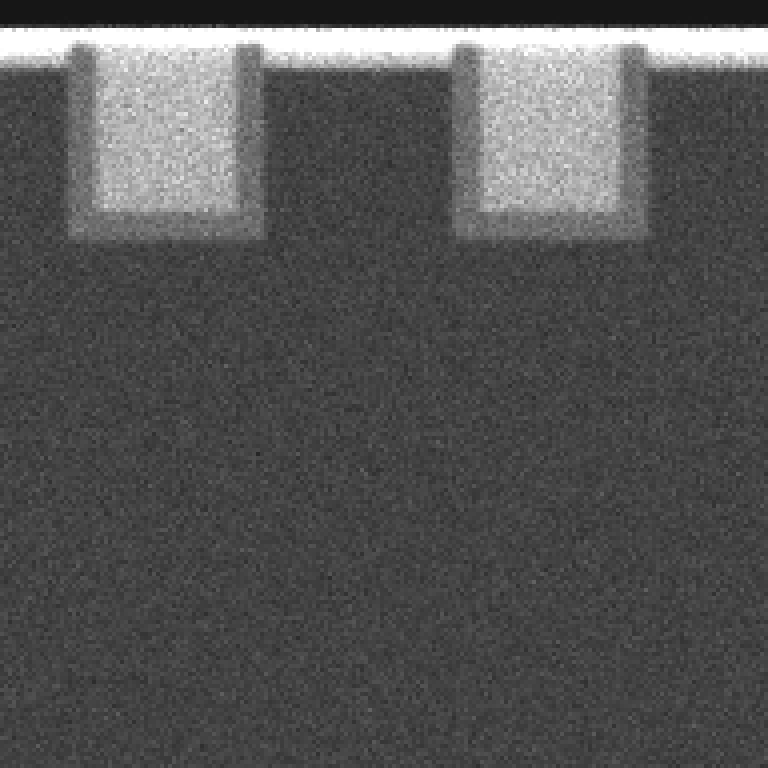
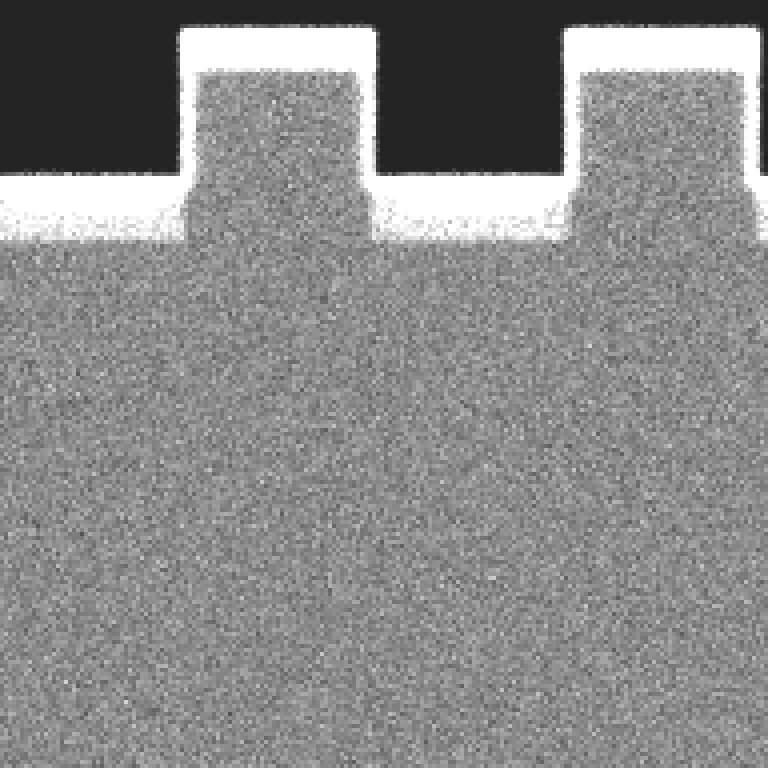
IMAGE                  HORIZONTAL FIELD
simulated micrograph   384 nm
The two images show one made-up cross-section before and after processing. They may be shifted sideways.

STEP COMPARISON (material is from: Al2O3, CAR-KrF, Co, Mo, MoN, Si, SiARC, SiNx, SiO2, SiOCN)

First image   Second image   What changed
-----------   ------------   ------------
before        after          Co and SiNx, removed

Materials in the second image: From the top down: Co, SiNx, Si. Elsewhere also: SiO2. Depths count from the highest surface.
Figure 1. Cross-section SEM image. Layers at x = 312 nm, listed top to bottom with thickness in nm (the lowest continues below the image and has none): SiO2 18, Si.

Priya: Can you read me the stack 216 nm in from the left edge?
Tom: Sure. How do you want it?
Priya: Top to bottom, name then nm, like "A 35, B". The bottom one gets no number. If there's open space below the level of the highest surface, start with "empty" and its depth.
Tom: empty 74, Co 16, SiNx 14, Si